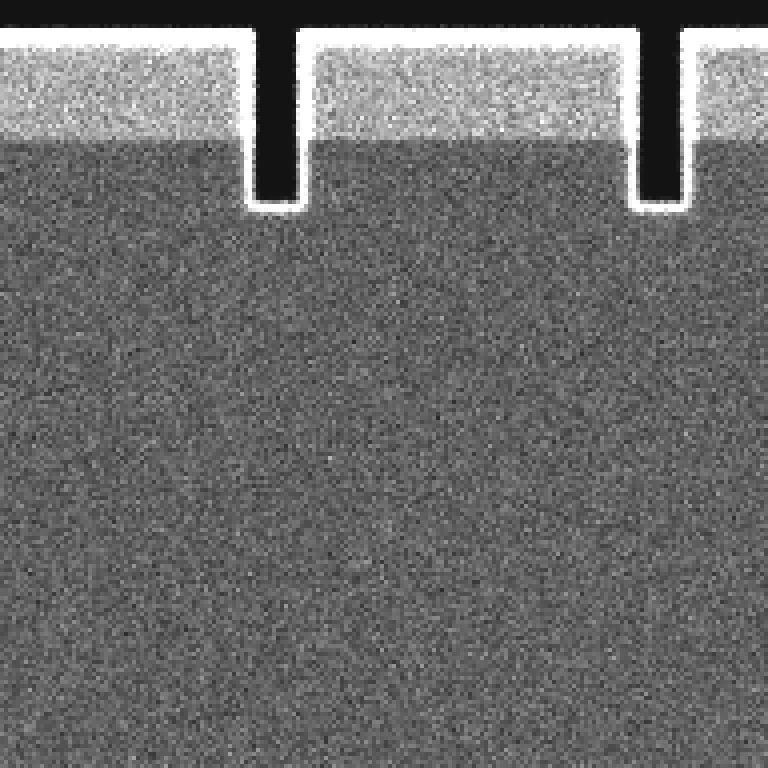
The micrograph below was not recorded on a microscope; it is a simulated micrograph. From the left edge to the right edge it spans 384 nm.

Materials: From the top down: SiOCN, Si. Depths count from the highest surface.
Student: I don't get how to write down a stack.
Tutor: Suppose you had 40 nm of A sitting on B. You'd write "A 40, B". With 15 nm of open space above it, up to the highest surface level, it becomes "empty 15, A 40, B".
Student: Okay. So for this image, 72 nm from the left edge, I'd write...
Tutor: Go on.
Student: SiOCN 54, Si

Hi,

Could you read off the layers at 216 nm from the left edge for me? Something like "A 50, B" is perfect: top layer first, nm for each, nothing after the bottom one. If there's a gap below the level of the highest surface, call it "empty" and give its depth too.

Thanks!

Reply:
SiOCN 54, Si